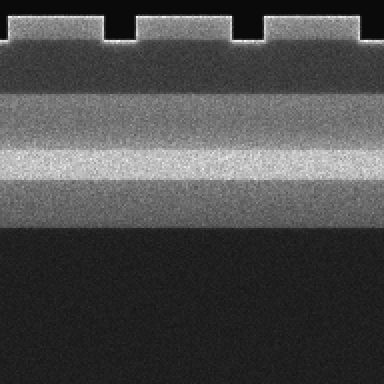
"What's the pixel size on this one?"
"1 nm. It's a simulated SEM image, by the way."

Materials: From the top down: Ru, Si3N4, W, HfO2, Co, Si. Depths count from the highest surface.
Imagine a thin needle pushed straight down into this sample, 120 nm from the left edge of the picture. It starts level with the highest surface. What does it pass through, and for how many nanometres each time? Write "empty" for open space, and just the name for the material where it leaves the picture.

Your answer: empty 24, Si3N4 54, W 56, HfO2 30, Co 48, Si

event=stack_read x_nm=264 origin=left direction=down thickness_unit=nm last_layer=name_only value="Ru 24, Si3N4 54, W 56, HfO2 30, Co 48, Si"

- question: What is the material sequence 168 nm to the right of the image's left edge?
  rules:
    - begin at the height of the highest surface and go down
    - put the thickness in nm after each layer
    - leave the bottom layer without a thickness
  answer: Ru 24, Si3N4 54, W 56, HfO2 30, Co 48, Si